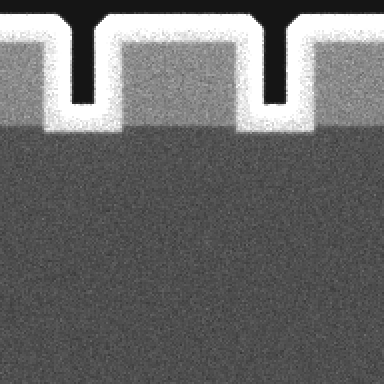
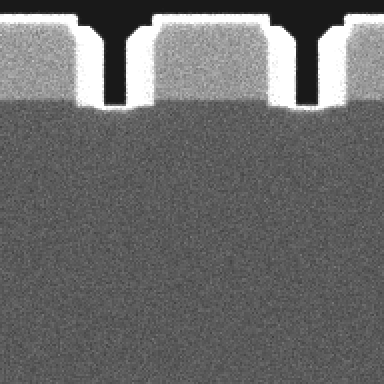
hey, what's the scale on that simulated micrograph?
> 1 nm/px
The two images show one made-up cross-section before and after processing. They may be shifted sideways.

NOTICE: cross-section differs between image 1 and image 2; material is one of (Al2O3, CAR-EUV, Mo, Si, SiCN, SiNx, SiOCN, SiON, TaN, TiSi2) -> removed: Al2O3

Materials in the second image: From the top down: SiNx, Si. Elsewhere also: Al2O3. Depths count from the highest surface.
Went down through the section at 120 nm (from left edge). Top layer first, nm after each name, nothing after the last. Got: empty 90, Si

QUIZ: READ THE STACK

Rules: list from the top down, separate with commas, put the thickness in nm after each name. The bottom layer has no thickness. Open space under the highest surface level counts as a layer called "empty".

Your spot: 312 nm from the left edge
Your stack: empty 90, Si